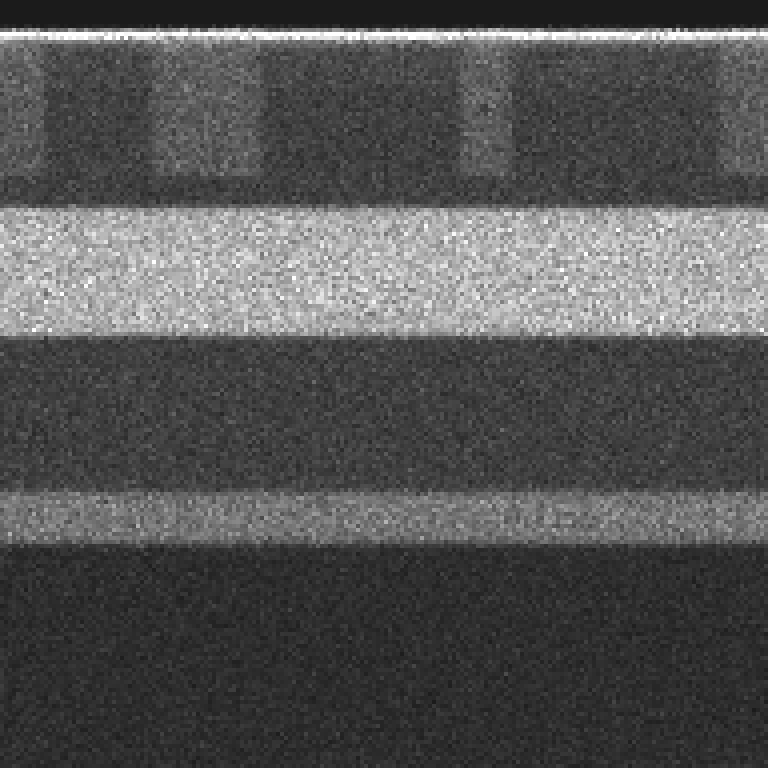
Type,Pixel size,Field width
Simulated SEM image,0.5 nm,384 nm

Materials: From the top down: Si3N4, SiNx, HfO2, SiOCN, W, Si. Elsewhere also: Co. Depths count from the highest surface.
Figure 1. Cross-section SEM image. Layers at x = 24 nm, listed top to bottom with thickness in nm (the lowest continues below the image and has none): Si3N4 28, SiNx 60, HfO2 64, SiOCN 78, W 26, Si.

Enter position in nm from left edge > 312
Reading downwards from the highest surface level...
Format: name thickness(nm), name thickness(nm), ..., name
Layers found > Si3N4 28, SiNx 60, HfO2 64, SiOCN 78, W 26, Si